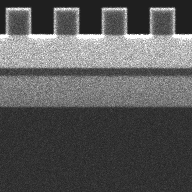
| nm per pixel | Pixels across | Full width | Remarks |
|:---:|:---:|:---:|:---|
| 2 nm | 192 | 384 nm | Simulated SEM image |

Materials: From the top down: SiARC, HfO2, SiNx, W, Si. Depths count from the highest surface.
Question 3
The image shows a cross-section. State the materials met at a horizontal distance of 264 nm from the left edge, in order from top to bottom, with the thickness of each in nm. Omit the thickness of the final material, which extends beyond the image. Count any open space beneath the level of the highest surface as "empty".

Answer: empty 54, HfO2 66, SiNx 16, W 62, Si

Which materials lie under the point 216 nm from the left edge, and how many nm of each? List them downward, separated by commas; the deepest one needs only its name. SiARC 54, HfO2 66, SiNx 16, W 62, Si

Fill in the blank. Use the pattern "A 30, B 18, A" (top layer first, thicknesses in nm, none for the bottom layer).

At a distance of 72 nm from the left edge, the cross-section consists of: empty 54, HfO2 66, SiNx 16, W 62, Si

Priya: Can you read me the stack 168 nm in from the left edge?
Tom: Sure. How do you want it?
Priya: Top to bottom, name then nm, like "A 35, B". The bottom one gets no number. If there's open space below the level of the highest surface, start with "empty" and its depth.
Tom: empty 54, HfO2 66, SiNx 16, W 62, Si